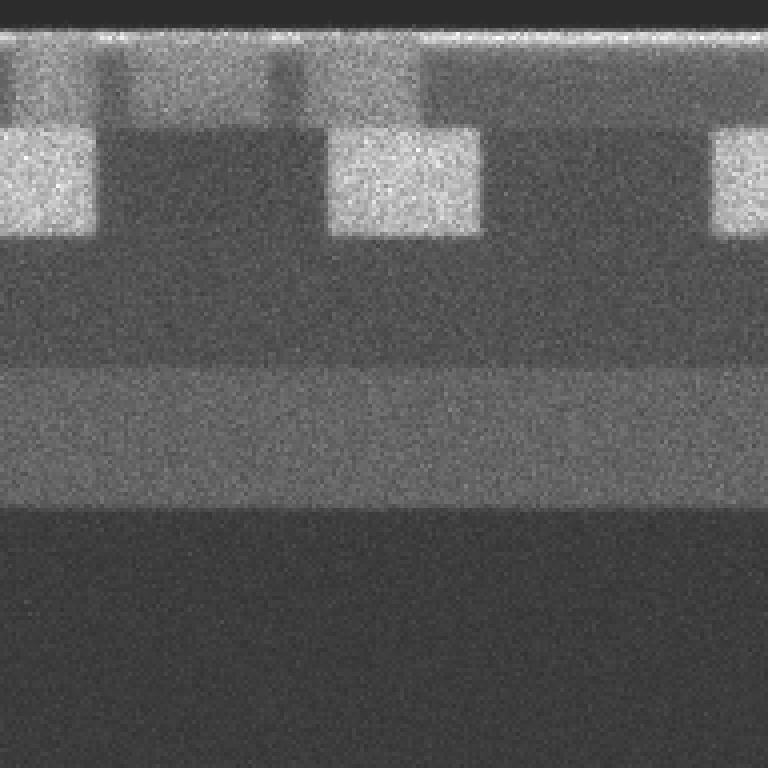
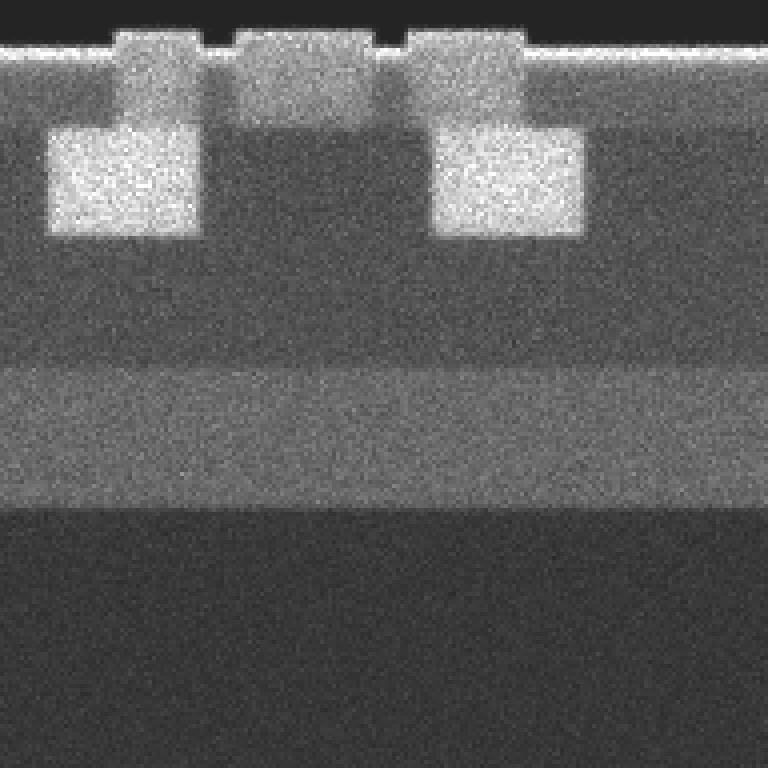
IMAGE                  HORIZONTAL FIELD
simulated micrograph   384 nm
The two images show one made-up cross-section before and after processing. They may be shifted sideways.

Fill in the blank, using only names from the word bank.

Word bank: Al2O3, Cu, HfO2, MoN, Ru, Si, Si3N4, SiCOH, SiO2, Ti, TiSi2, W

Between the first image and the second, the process removed SiO2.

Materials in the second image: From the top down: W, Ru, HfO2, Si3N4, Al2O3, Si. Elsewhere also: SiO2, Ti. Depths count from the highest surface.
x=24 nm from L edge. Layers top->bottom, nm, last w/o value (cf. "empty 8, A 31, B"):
empty 8, SiO2 40, HfO2 54, Si3N4 66, Al2O3 70, Si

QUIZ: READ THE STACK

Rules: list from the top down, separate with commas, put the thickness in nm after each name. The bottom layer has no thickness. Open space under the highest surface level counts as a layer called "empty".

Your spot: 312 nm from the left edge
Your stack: empty 8, SiO2 40, Ti 48, Si3N4 72, Al2O3 70, Si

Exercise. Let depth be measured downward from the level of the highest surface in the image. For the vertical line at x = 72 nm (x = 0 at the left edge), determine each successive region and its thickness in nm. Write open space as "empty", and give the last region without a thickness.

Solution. W 36, Ru 12, HfO2 54, Si3N4 66, Al2O3 70, Si